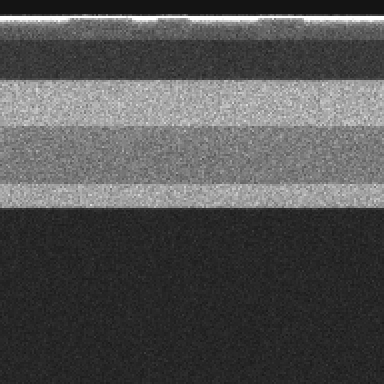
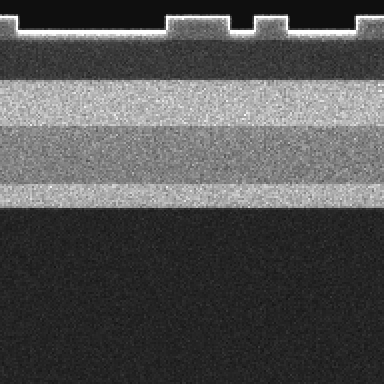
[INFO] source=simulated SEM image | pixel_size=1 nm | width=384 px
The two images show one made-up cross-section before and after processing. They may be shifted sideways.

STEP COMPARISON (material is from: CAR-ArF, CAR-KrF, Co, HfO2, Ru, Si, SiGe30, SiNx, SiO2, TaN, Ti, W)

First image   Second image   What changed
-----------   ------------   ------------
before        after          SiO2, removed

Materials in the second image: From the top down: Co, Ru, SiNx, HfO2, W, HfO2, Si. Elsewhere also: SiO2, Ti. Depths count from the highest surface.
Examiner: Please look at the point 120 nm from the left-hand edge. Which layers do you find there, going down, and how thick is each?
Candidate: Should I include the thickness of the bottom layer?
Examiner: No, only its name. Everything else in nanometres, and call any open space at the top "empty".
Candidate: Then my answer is empty 14, SiO2 10, SiNx 40, HfO2 46, W 58, HfO2 24, Si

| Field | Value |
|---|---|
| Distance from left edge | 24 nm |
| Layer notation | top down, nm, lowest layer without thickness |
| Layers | empty 14, SiO2 10, SiNx 40, HfO2 46, W 58, HfO2 24, Si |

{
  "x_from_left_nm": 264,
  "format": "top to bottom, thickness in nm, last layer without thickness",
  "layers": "Co 14, Ru 10, SiNx 40, HfO2 46, W 58, HfO2 24, Si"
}